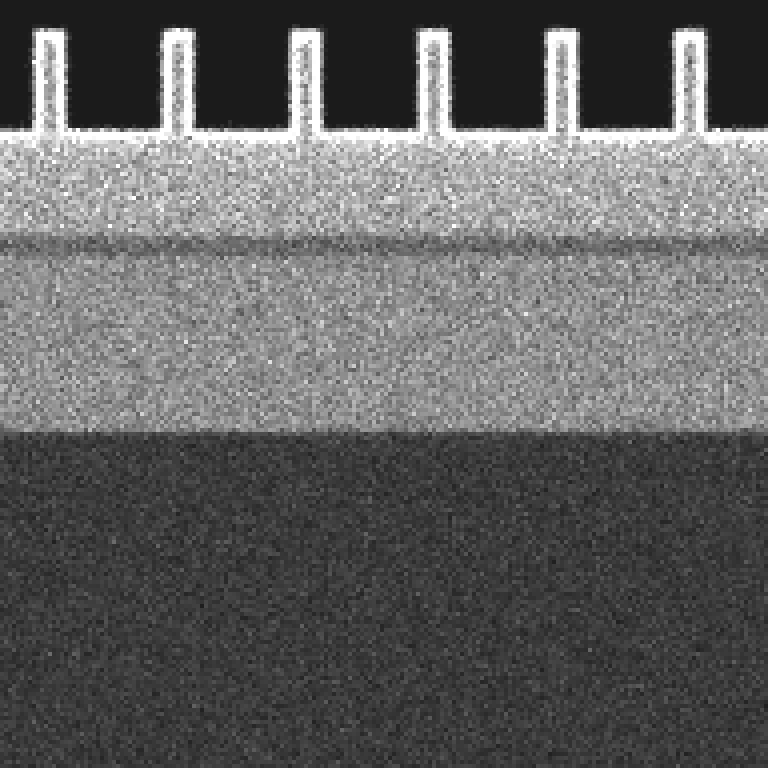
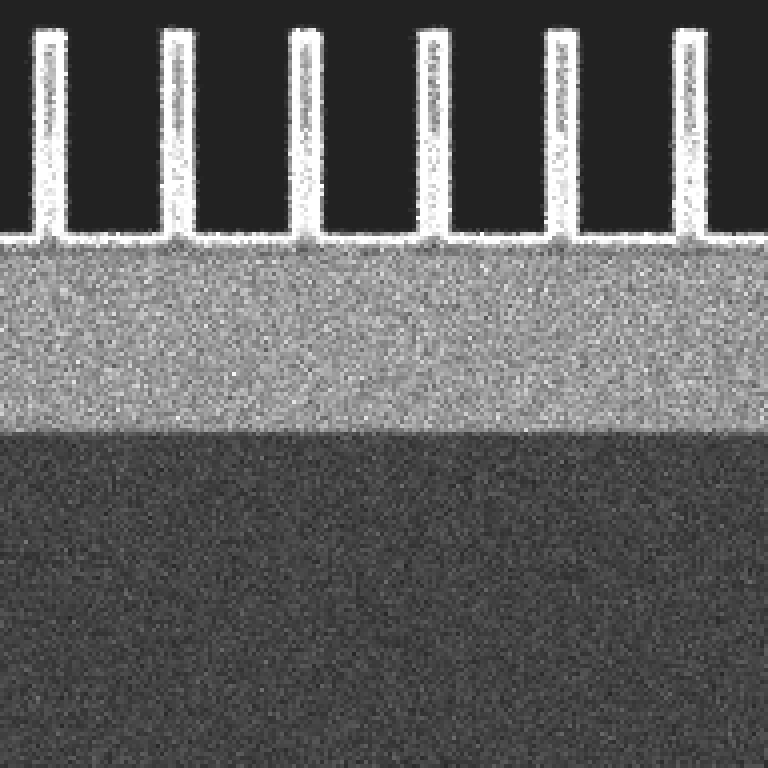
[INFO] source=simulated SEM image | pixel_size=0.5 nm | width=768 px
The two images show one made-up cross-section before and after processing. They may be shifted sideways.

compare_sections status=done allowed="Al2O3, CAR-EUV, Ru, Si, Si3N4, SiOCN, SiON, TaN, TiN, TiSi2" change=removed material="Ru"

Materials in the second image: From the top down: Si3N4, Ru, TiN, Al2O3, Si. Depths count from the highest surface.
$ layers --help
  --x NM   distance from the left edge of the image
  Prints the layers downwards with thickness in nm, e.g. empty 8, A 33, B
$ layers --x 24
Si3N4 50, Ru 52, TiN 10, Al2O3 88, Si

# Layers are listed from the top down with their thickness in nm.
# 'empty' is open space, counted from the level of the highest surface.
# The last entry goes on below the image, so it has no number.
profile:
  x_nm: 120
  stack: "empty 102, TiN 10, Al2O3 88, Si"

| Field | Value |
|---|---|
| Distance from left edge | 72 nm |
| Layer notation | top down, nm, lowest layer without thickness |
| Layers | empty 102, TiN 10, Al2O3 88, Si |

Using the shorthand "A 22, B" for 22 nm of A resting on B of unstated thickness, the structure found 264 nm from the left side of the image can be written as empty 102, TiN 10, Al2O3 88, Si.